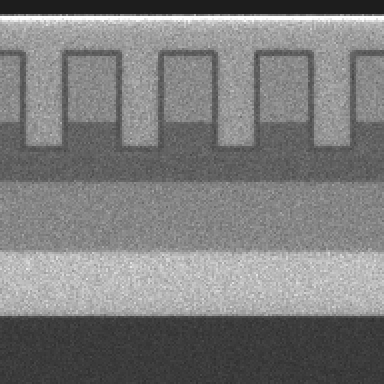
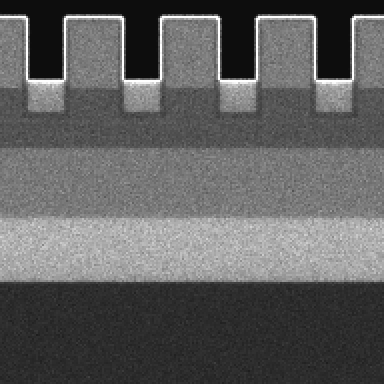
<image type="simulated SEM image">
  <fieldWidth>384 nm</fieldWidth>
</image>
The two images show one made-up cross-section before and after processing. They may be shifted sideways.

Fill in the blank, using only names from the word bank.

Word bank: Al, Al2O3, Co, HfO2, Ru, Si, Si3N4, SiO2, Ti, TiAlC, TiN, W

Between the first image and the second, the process removed Ru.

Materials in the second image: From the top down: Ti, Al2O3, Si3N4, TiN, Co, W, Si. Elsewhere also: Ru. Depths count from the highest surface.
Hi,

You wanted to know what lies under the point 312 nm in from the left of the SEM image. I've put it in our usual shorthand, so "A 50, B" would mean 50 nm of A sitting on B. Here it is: Ti 102, Si3N4 6, TiN 24, Co 70, W 64, Si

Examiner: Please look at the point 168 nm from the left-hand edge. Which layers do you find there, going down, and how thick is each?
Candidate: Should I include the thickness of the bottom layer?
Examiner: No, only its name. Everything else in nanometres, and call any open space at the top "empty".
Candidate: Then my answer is Ti 6, Al2O3 66, Si3N4 36, TiN 24, Co 70, W 64, Si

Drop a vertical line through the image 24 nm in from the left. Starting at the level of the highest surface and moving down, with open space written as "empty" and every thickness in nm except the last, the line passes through Ti 102, Si3N4 6, TiN 24, Co 70, W 64, Si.